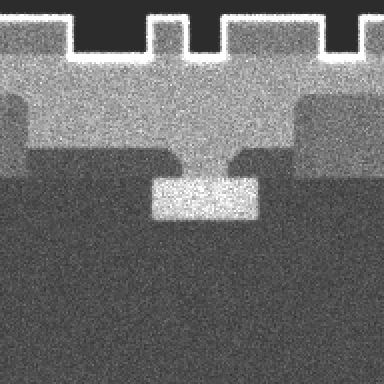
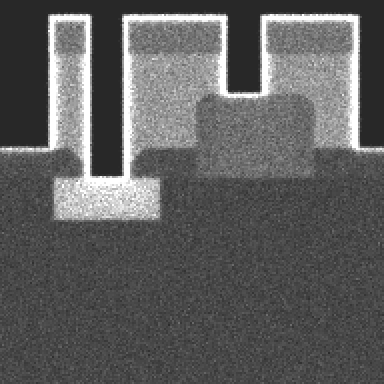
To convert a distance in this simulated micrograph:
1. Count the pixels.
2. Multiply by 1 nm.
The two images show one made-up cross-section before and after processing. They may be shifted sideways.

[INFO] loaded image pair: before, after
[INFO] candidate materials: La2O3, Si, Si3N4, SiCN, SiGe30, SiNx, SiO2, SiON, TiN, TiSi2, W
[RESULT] removed SiO2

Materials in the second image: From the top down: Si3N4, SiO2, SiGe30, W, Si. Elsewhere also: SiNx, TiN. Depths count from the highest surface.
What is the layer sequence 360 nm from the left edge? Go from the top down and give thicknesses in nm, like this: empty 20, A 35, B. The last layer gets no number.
empty 132, SiGe30 30, Si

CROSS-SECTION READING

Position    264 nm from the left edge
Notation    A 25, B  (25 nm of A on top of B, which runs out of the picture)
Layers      Si3N4 38, SiO2 40, TiN 84, Si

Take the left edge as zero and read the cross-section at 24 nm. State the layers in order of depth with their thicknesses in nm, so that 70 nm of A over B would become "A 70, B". empty 132, SiGe30 30, Si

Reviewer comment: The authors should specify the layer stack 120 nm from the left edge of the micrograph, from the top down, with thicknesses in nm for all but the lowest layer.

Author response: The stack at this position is empty 162, W 42, Si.